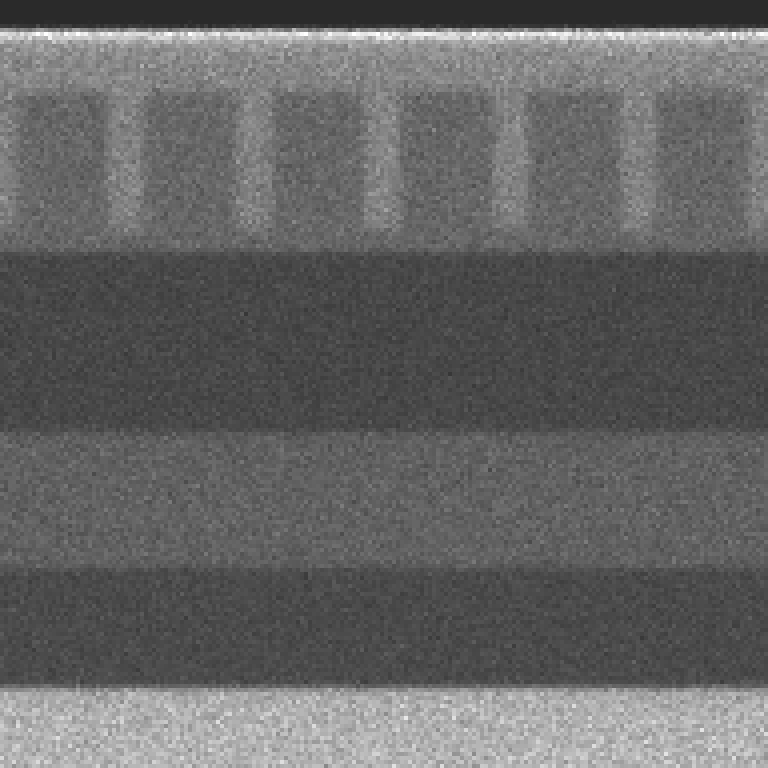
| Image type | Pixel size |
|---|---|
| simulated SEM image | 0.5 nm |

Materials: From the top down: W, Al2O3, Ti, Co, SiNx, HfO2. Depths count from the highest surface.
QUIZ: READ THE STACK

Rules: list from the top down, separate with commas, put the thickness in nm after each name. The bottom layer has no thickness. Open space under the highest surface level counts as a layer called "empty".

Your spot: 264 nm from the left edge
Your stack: W 30, Al2O3 80, Ti 90, Co 68, SiNx 60, HfO2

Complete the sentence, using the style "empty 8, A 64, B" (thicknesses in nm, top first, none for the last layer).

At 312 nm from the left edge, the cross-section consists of W 100, Al2O3 10, Ti 90, Co 68, SiNx 60, HfO2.